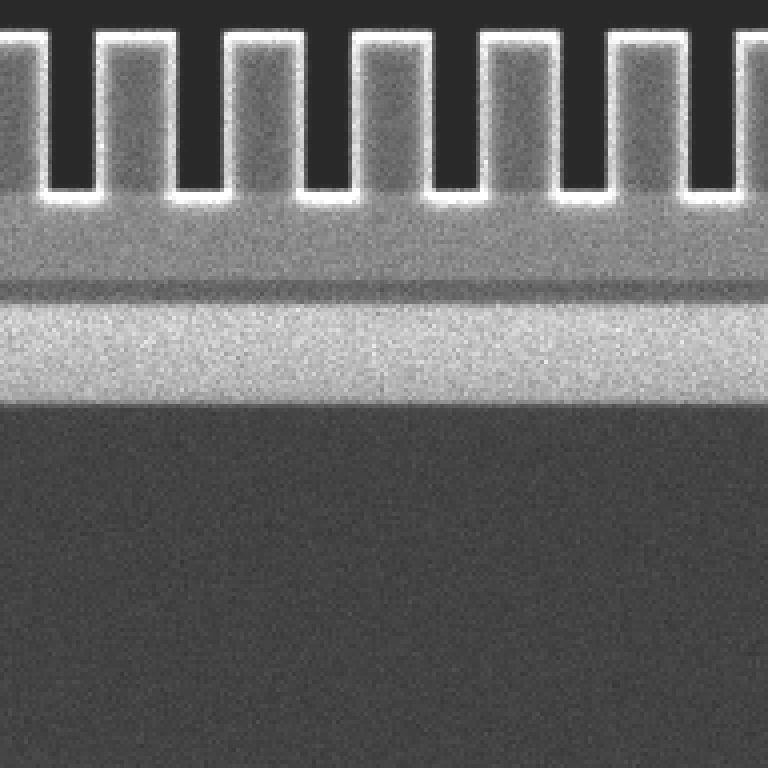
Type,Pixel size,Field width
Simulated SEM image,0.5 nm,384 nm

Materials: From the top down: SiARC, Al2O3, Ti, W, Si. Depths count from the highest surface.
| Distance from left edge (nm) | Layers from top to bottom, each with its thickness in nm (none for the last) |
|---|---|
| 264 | SiARC 80, Al2O3 44, Ti 12, W 50, Si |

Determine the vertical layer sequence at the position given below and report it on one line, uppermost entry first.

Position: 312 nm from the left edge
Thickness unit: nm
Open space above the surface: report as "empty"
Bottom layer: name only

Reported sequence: SiARC 80, Al2O3 44, Ti 12, W 50, Si